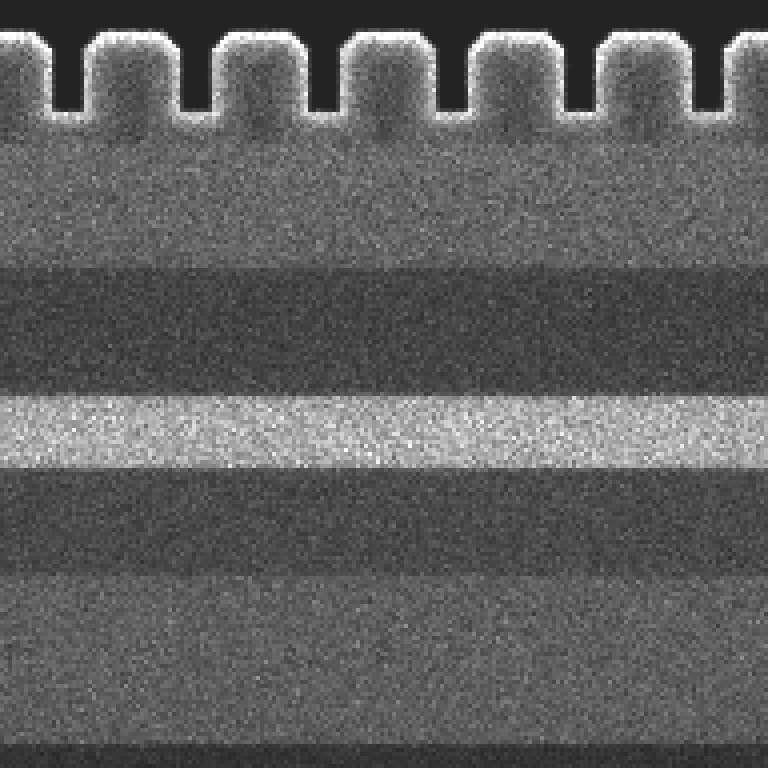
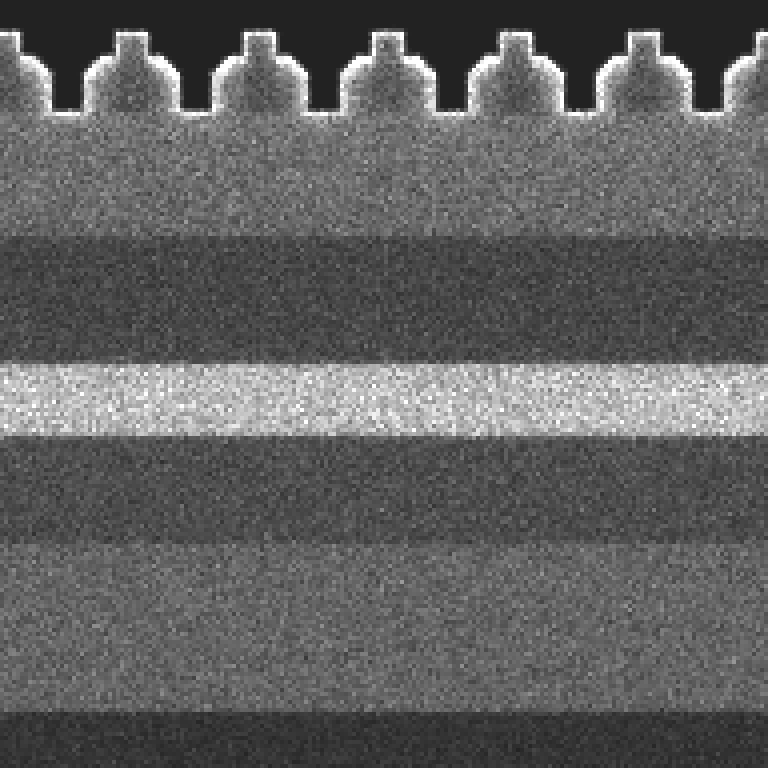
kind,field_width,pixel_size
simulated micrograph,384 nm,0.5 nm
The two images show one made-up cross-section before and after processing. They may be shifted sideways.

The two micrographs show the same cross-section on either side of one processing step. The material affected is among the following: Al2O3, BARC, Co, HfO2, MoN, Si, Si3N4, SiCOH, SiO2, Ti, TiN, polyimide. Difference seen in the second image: SiO2 removed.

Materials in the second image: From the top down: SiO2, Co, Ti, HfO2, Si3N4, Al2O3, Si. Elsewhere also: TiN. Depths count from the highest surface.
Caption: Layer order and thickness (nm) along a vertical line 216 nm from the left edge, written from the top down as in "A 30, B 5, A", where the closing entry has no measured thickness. empty 20, SiO2 20, Co 62, Ti 64, HfO2 36, Si3N4 54, Al2O3 84, Si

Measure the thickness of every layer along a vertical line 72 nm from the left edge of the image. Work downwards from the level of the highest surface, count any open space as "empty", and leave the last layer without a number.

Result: TiN 40, Co 62, Ti 64, HfO2 36, Si3N4 54, Al2O3 84, Si